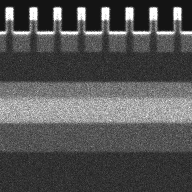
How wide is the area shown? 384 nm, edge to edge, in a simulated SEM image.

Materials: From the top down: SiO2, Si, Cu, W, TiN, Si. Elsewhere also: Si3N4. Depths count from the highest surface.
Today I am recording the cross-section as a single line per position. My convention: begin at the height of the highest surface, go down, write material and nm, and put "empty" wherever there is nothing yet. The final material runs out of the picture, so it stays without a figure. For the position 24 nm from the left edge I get SiO2 24, Si 124, Cu 32, W 50, TiN 58, Si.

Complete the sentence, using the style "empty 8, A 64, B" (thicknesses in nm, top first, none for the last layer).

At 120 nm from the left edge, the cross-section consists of SiO2 24, Si 124, Cu 32, W 50, TiN 58, Si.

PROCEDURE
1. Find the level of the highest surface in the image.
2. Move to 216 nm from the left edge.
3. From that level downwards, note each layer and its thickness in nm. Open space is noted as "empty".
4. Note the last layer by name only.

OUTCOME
SiO2 24, Si 124, Cu 32, W 50, TiN 58, Si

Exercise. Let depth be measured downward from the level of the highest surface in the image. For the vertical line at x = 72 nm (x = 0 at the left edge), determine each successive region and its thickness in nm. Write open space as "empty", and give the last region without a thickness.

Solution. SiO2 24, Si 124, Cu 32, W 50, TiN 58, Si